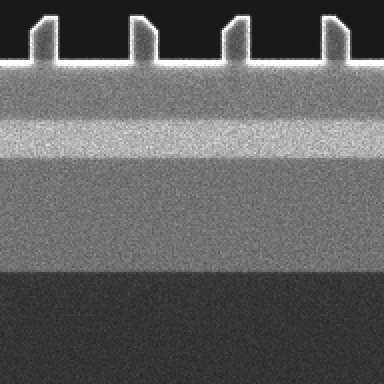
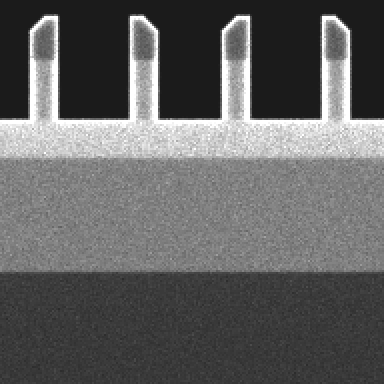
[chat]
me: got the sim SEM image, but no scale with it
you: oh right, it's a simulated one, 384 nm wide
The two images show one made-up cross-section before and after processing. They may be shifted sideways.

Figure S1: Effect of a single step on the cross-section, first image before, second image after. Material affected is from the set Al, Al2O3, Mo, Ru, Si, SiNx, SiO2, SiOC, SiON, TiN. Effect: removed Al2O3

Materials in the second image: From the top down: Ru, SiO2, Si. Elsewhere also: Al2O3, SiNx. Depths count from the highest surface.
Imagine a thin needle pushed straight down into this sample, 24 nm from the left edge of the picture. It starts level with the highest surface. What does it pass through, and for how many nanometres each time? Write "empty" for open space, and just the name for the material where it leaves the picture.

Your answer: empty 104, Ru 38, SiO2 114, Si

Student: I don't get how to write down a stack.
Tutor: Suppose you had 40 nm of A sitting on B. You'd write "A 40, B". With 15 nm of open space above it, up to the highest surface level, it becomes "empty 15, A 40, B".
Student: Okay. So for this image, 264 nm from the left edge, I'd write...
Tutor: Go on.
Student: empty 104, Ru 38, SiO2 114, Si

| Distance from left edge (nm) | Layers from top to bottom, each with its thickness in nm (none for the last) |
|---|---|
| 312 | empty 104, Ru 38, SiO2 114, Si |